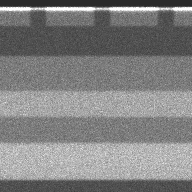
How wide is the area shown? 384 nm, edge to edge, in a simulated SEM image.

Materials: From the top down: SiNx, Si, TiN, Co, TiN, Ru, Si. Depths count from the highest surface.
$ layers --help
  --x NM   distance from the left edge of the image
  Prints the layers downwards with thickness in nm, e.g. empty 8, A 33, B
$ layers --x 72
Si 96, TiN 70, Co 52, TiN 52, Ru 74, Si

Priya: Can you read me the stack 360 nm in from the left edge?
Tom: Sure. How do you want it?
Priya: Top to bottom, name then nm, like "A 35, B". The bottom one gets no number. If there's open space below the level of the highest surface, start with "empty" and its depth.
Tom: SiNx 36, Si 60, TiN 70, Co 52, TiN 52, Ru 74, Si